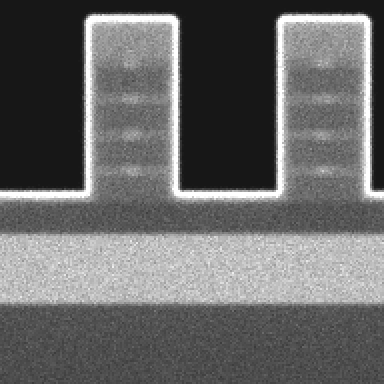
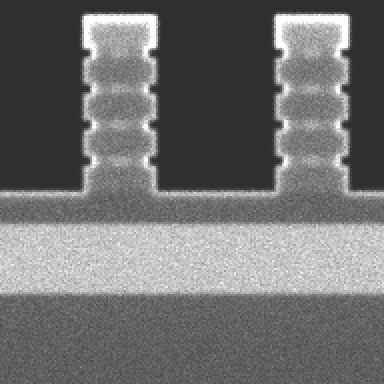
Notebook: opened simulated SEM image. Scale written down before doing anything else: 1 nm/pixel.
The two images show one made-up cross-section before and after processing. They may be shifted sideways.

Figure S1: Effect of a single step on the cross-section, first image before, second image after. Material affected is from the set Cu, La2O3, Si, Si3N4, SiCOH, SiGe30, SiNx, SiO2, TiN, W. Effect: removed SiNx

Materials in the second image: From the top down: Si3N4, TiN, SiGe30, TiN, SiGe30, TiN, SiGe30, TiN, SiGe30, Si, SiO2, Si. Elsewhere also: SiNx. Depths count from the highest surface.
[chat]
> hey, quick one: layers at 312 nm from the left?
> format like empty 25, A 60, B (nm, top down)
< Si3N4 32, TiN 10, SiGe30 26, TiN 10, SiGe30 26, TiN 10, SiGe30 26, TiN 10, SiGe30 26, Si 32, SiO2 70, Si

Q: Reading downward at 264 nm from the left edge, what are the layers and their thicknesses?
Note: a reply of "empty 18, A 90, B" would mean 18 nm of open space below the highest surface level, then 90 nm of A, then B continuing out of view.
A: empty 176, Si 32, SiO2 70, Si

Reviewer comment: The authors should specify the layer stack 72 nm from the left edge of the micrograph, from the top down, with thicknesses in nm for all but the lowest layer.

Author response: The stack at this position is empty 176, Si 32, SiO2 70, Si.